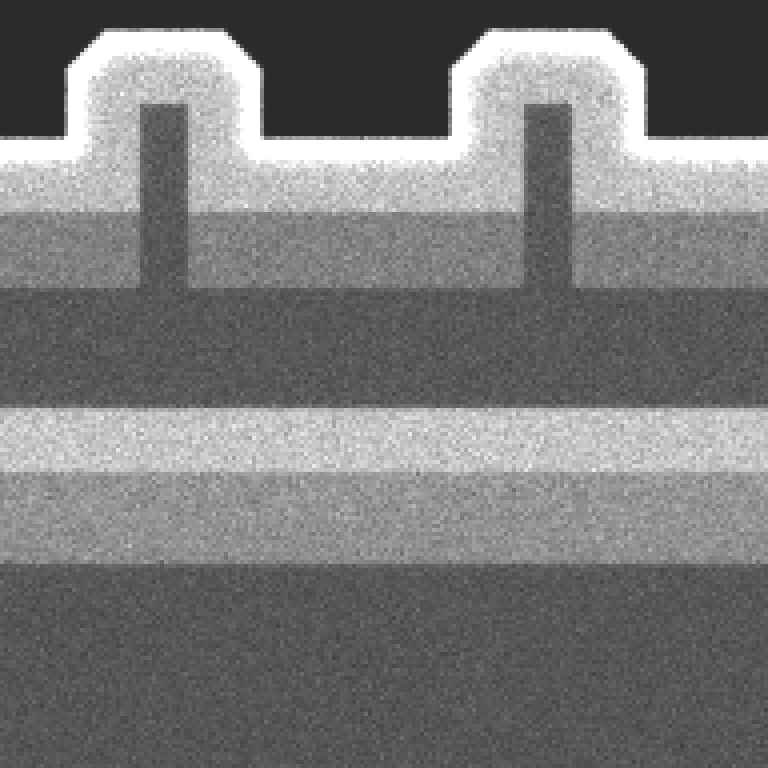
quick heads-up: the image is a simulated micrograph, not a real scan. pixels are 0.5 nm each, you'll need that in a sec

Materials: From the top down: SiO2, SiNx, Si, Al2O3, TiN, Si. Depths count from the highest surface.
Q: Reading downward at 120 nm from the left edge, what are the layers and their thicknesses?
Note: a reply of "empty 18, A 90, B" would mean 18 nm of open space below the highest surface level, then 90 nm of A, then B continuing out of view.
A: empty 10, SiO2 80, SiNx 38, Si 60, Al2O3 32, TiN 46, Si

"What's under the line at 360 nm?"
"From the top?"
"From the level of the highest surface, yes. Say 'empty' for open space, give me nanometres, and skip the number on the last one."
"empty 54, SiO2 36, SiNx 38, Si 60, Al2O3 32, TiN 46, Si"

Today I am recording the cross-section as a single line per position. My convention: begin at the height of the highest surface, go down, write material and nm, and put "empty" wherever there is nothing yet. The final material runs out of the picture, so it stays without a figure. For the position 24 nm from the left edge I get empty 54, SiO2 36, SiNx 38, Si 60, Al2O3 32, TiN 46, Si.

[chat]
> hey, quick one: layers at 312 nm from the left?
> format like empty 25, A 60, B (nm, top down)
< empty 10, SiO2 80, SiNx 38, Si 60, Al2O3 32, TiN 46, Si